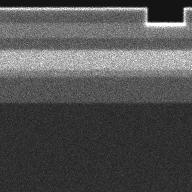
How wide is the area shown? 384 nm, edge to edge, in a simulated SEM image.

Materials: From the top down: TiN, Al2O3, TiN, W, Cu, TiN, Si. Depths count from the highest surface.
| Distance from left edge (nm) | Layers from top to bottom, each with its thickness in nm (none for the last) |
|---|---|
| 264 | TiN 30, Al2O3 30, TiN 24, W 40, Cu 14, TiN 52, Si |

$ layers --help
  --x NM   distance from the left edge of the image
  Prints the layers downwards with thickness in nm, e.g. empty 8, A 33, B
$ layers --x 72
TiN 30, Al2O3 30, TiN 24, W 40, Cu 14, TiN 52, Si